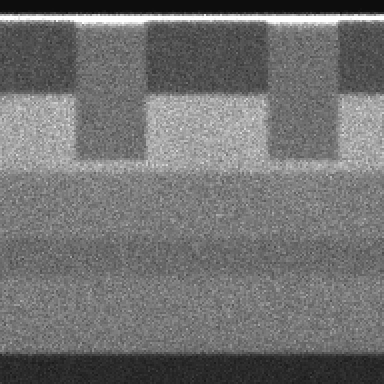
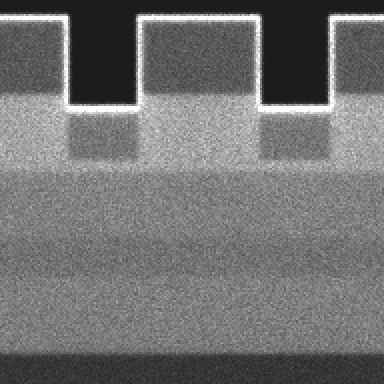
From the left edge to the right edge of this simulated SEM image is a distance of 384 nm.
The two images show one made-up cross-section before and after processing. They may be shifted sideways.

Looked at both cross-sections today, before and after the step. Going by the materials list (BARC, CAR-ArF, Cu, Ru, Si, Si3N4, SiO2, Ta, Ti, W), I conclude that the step removed SiO2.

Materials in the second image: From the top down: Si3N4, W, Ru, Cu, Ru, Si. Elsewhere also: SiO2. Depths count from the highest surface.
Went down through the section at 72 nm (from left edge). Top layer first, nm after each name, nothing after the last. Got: empty 90, SiO2 54, W 12, Ru 66, Cu 38, Ru 78, Si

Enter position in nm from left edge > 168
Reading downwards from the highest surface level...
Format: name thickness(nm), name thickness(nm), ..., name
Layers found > Si3N4 78, W 78, Ru 66, Cu 38, Ru 78, Si